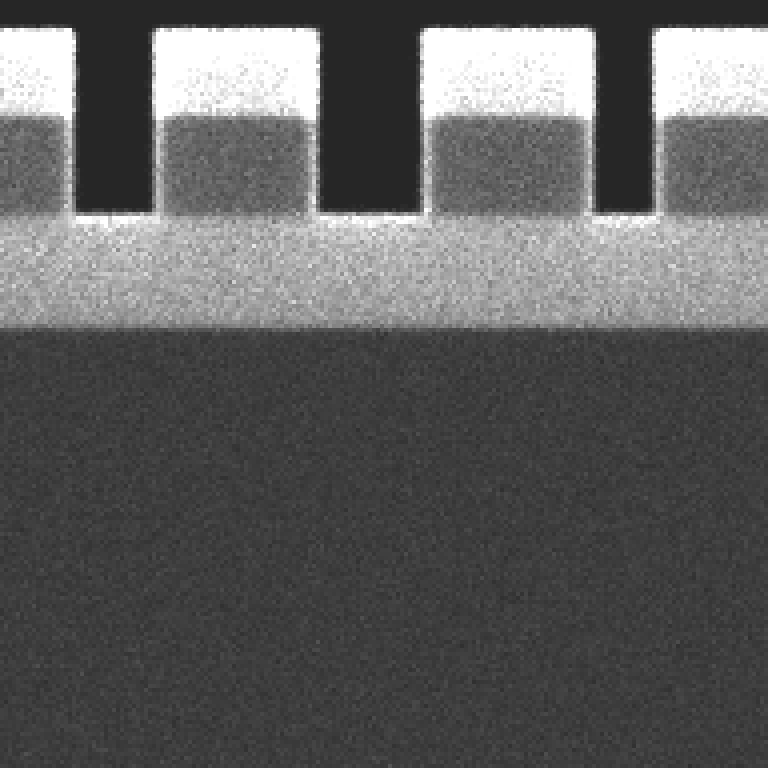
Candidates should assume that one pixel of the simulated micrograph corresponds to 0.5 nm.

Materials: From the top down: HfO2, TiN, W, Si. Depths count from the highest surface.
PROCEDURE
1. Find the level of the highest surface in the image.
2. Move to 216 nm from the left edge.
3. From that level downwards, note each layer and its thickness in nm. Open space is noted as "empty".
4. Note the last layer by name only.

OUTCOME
HfO2 42, TiN 50, W 56, Si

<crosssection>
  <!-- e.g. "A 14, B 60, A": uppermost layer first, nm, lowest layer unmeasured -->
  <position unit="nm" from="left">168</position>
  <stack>empty 92, W 56, Si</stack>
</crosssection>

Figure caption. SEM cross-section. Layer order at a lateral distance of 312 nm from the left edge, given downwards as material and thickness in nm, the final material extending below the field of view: empty 92, W 56, Si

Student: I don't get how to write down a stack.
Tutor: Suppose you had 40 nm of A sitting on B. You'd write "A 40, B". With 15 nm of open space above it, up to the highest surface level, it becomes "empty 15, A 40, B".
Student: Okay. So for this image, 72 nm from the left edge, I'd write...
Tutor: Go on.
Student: empty 92, W 56, Si